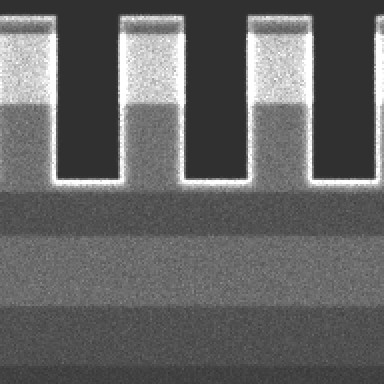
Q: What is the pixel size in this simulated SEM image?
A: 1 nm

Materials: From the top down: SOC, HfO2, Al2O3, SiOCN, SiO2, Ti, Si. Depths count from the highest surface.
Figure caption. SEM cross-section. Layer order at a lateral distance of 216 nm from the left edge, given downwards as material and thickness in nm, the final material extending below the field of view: empty 164, Al2O3 12, SiOCN 44, SiO2 70, Ti 60, Si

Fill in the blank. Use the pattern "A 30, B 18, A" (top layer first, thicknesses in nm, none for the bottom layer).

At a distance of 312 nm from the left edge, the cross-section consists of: empty 164, Al2O3 12, SiOCN 44, SiO2 70, Ti 60, Si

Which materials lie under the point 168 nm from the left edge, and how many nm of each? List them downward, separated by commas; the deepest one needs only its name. SOC 18, HfO2 70, Al2O3 88, SiOCN 44, SiO2 70, Ti 60, Si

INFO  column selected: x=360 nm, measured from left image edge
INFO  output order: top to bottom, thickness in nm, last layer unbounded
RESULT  empty 164, Al2O3 12, SiOCN 44, SiO2 70, Ti 60, Si